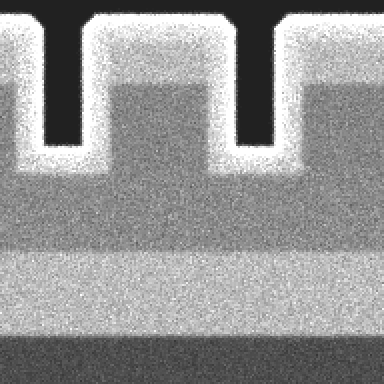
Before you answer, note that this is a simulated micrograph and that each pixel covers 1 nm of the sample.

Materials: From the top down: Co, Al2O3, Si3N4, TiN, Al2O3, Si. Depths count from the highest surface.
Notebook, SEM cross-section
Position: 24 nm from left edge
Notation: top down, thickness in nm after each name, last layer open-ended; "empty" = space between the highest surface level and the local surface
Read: Co 158, TiN 78, Al2O3 84, Si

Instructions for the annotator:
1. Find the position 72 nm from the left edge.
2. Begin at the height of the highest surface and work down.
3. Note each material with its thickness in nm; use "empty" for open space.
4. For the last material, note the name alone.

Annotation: empty 132, Co 26, TiN 78, Al2O3 84, Si